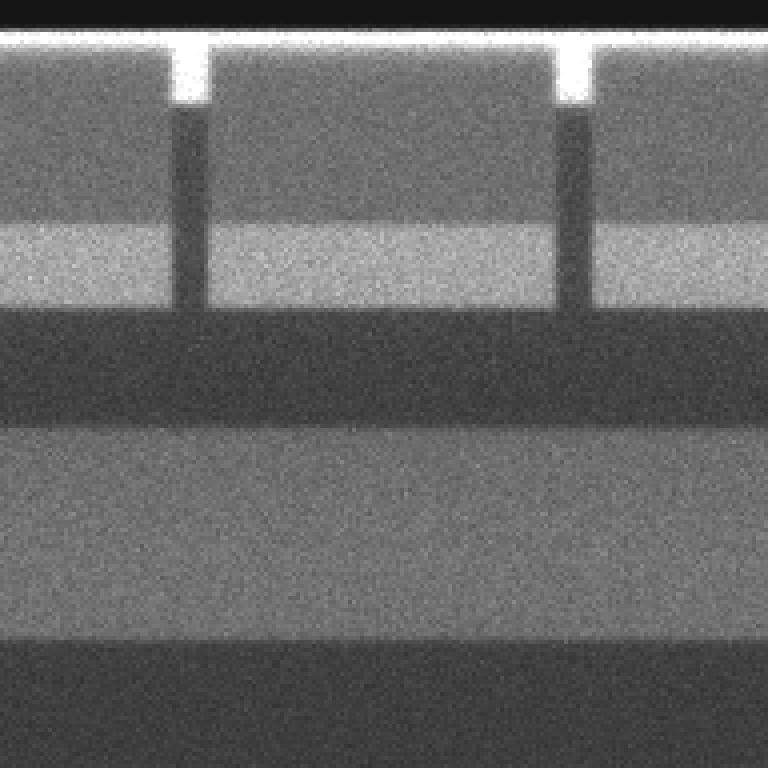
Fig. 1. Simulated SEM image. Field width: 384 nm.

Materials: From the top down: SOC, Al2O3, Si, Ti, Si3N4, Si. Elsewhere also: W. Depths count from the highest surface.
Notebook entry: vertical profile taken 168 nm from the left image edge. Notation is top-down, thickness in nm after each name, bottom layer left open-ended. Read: SOC 96, Al2O3 42, Si 60, Ti 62, Si3N4 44, Si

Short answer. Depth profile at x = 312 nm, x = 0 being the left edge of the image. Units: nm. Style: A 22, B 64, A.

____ SOC 96, Al2O3 42, Si 60, Ti 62, Si3N4 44, Si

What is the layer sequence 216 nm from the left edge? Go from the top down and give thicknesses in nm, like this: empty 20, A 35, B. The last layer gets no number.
SOC 96, Al2O3 42, Si 60, Ti 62, Si3N4 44, Si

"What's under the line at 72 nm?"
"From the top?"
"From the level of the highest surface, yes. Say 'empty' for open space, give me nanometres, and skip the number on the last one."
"SOC 96, Al2O3 42, Si 60, Ti 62, Si3N4 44, Si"